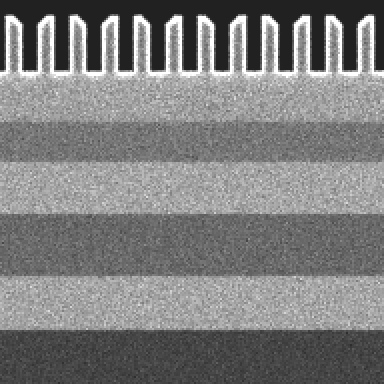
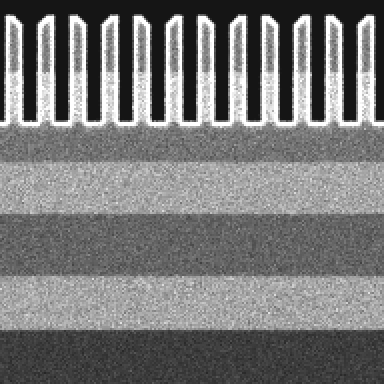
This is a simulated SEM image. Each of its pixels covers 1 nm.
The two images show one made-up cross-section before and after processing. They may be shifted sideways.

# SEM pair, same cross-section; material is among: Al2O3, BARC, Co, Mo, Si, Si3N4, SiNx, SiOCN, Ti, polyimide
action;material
removed;Co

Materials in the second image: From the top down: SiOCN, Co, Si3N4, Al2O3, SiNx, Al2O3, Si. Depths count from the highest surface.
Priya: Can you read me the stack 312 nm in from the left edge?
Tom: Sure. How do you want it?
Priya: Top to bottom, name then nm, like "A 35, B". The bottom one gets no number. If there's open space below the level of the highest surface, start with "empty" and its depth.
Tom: empty 106, Si3N4 40, Al2O3 52, SiNx 62, Al2O3 54, Si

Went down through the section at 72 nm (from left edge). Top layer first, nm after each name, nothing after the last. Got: SiOCN 56, Co 50, Si3N4 40, Al2O3 52, SiNx 62, Al2O3 54, Si